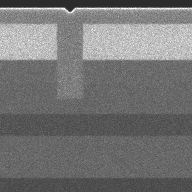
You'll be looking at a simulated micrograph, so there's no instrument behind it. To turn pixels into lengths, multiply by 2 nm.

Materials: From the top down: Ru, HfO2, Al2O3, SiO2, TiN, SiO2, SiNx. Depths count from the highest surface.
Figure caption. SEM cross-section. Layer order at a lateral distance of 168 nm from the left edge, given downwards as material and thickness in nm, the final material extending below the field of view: Ru 32, HfO2 72, Al2O3 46, SiO2 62, TiN 44, SiO2 84, SiNx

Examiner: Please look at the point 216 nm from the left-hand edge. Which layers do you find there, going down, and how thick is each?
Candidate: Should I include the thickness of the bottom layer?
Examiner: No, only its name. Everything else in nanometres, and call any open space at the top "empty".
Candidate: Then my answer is Ru 32, HfO2 72, Al2O3 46, SiO2 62, TiN 44, SiO2 84, SiNx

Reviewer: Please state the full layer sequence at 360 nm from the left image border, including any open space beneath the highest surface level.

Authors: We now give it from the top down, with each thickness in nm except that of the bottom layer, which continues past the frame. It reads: Ru 32, HfO2 72, Al2O3 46, SiO2 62, TiN 44, SiO2 84, SiNx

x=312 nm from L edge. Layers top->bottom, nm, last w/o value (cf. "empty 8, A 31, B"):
Ru 32, HfO2 72, Al2O3 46, SiO2 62, TiN 44, SiO2 84, SiNx